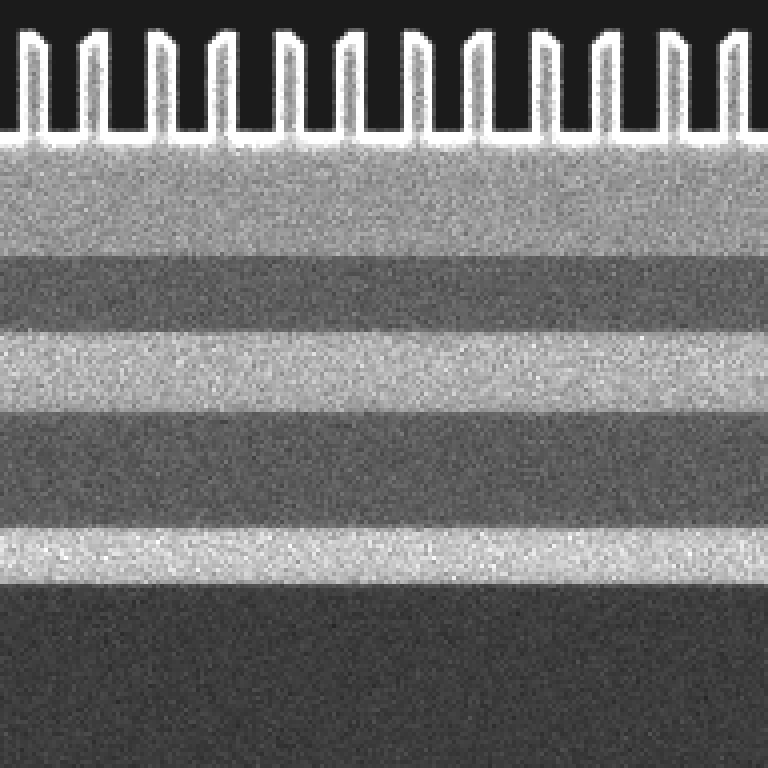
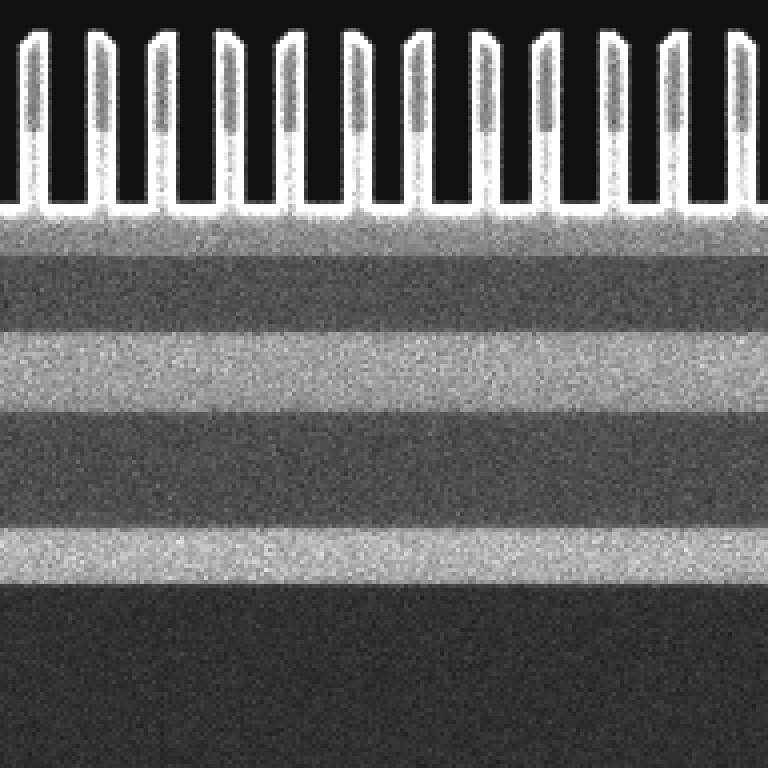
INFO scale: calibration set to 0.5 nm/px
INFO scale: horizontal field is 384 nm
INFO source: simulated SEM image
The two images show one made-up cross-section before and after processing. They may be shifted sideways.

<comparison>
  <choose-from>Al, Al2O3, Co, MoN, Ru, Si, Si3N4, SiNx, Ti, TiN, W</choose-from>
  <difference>Al2O3 removed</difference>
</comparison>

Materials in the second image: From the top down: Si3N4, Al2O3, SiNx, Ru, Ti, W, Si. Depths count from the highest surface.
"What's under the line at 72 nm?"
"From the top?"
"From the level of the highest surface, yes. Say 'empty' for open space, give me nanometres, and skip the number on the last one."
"empty 86, Al2O3 26, SiNx 38, Ru 40, Ti 58, W 28, Si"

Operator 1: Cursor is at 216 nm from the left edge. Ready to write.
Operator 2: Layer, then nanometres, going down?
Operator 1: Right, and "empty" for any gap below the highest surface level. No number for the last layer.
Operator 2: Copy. empty 86, Al2O3 26, SiNx 38, Ru 40, Ti 58, W 28, Si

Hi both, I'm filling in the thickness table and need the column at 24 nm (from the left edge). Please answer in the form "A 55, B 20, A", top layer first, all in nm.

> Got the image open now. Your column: empty 86, Al2O3 26, SiNx 38, Ru 40, Ti 58, W 28, Si